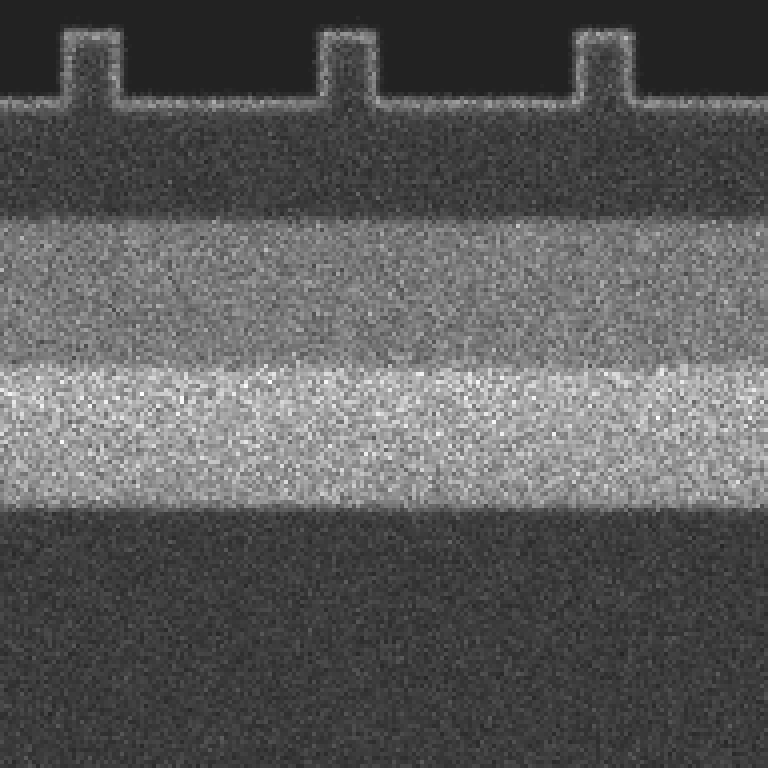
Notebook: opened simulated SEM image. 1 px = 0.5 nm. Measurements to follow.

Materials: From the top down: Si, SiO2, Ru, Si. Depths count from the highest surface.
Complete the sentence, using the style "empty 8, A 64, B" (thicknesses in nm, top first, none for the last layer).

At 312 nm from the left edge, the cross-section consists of Si 94, SiO2 74, Ru 70, Si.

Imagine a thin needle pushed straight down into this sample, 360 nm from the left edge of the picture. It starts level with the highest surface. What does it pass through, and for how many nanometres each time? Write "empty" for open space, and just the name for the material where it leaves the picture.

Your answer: empty 34, Si 60, SiO2 74, Ru 70, Si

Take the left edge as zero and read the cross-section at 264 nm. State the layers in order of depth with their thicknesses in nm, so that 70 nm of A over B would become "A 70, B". empty 34, Si 60, SiO2 74, Ru 70, Si